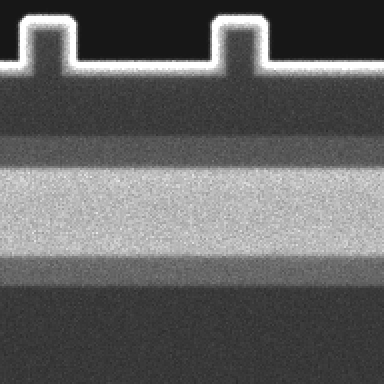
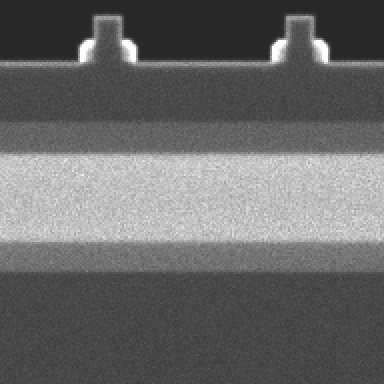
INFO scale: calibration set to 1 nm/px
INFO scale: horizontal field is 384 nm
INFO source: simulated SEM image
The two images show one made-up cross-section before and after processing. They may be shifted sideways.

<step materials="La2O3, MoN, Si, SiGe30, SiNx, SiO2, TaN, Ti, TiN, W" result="removed SiO2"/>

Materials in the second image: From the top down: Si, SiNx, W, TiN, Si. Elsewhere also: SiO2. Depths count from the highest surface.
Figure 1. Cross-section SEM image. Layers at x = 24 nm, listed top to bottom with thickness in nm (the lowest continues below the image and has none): empty 46, Si 60, SiNx 32, W 88, TiN 30, Si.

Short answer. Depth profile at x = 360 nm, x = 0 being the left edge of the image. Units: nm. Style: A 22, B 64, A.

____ empty 46, Si 60, SiNx 32, W 88, TiN 30, Si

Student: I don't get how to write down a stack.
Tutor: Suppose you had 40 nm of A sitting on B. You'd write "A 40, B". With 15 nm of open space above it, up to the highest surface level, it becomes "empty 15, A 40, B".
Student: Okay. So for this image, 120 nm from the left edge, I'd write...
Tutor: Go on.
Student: Si 106, SiNx 32, W 88, TiN 30, Si